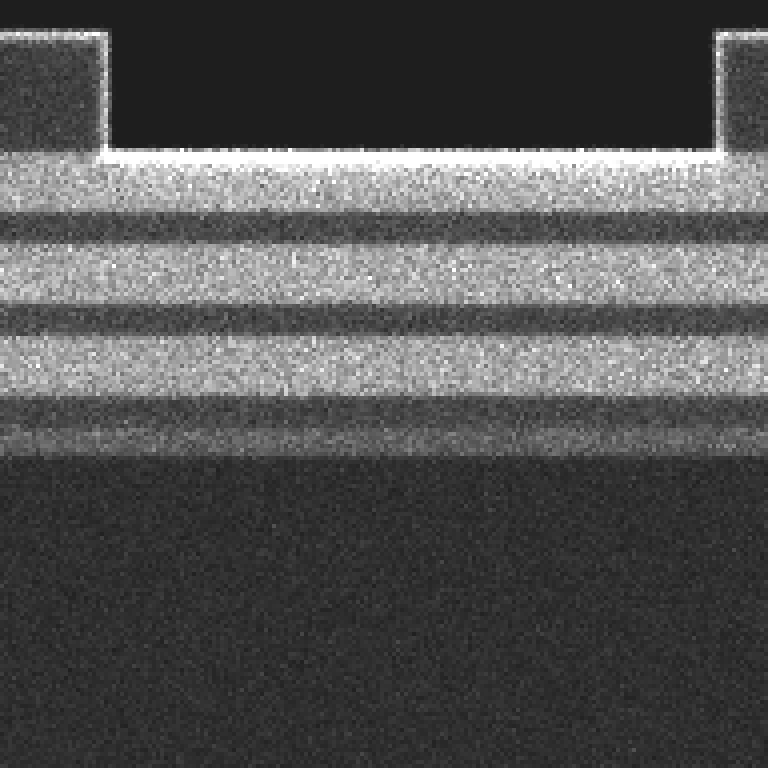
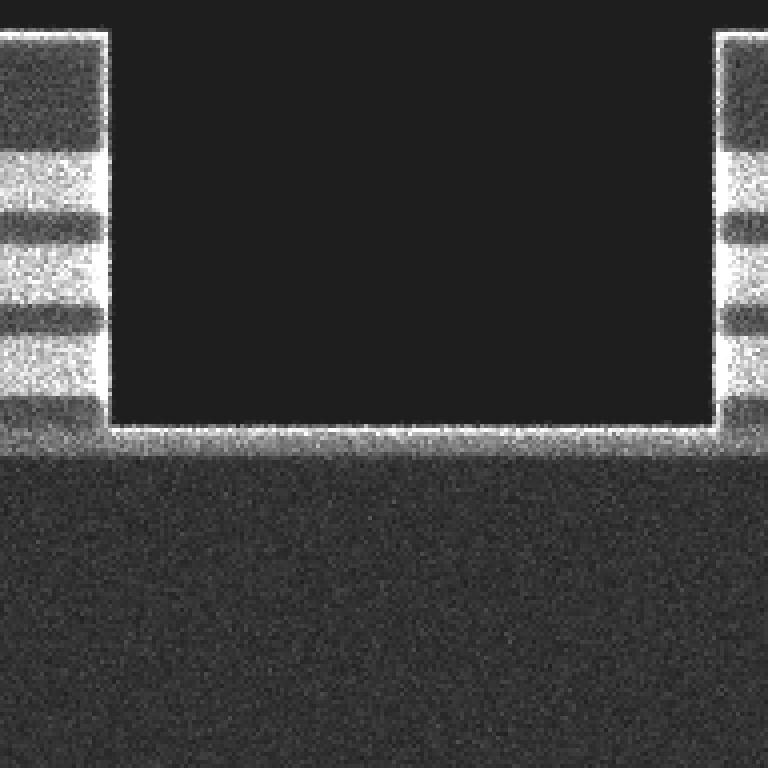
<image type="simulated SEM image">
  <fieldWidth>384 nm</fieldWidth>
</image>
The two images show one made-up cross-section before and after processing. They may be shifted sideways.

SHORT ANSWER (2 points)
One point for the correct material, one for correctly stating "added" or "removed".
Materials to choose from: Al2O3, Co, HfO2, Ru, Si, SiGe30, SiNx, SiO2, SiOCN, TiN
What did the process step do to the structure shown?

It removed HfO2 and TiN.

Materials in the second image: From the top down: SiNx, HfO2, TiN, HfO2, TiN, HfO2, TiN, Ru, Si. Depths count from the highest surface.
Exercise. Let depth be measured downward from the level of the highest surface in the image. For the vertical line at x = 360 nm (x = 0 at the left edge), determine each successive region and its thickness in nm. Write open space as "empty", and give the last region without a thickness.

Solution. SiNx 60, HfO2 30, TiN 16, HfO2 30, TiN 16, HfO2 30, TiN 16, Ru 14, Si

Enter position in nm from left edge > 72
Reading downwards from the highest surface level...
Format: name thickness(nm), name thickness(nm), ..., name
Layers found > empty 198, Ru 14, Si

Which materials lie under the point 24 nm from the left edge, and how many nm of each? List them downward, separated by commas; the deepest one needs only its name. SiNx 60, HfO2 30, TiN 16, HfO2 30, TiN 16, HfO2 30, TiN 16, Ru 14, Si